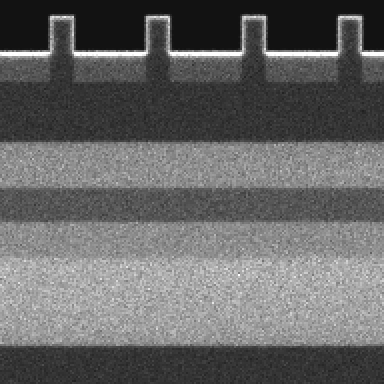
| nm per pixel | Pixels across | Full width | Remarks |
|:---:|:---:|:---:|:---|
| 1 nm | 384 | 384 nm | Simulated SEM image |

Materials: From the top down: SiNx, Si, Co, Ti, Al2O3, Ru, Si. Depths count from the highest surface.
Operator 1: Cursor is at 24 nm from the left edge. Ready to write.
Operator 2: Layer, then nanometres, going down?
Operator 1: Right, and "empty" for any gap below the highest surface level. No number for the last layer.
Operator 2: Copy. empty 36, SiNx 30, Si 60, Co 46, Ti 34, Al2O3 36, Ru 88, Si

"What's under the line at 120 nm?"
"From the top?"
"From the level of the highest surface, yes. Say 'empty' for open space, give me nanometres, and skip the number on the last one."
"empty 36, SiNx 30, Si 60, Co 46, Ti 34, Al2O3 36, Ru 88, Si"